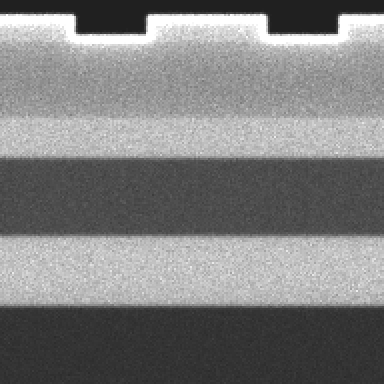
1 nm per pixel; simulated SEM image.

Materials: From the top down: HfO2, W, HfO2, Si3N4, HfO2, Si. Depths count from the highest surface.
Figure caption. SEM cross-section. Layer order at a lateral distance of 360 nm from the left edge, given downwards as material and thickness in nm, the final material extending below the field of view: HfO2 26, W 76, HfO2 40, Si3N4 78, HfO2 70, Si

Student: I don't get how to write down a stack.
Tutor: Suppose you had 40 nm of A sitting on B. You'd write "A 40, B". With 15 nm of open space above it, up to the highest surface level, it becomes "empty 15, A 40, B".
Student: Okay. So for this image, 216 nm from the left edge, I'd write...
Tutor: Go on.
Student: HfO2 26, W 76, HfO2 40, Si3N4 78, HfO2 70, Si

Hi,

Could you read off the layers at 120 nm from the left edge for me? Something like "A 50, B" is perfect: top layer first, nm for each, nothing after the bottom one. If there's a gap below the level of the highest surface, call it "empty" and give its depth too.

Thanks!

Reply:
empty 20, HfO2 6, W 76, HfO2 40, Si3N4 78, HfO2 70, Si